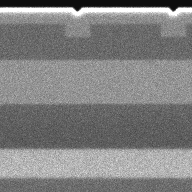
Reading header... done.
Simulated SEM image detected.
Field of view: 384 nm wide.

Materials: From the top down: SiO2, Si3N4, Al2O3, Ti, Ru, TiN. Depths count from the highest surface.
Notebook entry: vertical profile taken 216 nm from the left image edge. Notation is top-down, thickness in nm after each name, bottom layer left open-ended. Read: SiO2 32, Si3N4 72, Al2O3 88, Ti 90, Ru 58, TiN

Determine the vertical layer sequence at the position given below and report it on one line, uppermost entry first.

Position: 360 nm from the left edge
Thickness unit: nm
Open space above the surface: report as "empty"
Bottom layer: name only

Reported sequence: SiO2 58, Si3N4 46, Al2O3 88, Ti 90, Ru 58, TiN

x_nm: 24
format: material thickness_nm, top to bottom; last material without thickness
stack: SiO2 32, Si3N4 72, Al2O3 88, Ti 90, Ru 58, TiN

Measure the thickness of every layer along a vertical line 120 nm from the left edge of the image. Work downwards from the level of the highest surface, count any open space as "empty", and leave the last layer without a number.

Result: SiO2 32, Si3N4 72, Al2O3 88, Ti 90, Ru 58, TiN